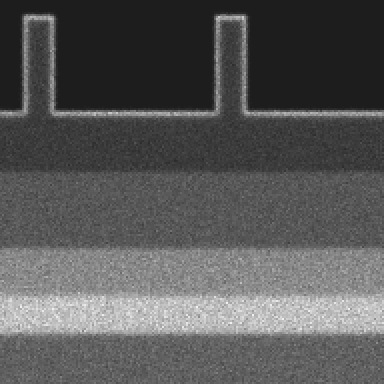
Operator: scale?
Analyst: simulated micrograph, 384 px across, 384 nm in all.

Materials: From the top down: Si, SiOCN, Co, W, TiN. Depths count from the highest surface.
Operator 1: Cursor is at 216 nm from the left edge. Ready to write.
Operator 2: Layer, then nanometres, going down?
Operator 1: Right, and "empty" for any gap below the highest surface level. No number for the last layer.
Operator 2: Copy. Si 156, SiOCN 76, Co 48, W 38, TiN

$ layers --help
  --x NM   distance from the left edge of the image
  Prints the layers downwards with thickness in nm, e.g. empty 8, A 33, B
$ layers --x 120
empty 96, Si 60, SiOCN 76, Co 48, W 38, TiN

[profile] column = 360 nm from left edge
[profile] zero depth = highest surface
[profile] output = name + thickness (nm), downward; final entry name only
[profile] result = empty 96, Si 60, SiOCN 76, Co 48, W 38, TiN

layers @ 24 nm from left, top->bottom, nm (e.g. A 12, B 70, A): Si 156, SiOCN 76, Co 48, W 38, TiN